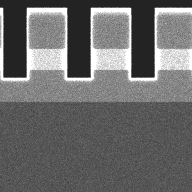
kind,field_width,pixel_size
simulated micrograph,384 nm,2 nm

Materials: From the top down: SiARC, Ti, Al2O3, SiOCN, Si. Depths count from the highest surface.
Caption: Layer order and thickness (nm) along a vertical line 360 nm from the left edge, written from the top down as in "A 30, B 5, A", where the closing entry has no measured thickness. SiARC 14, Ti 68, Al2O3 42, SiOCN 64, Si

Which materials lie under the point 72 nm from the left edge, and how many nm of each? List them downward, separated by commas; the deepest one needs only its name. SiARC 14, Ti 68, Al2O3 42, SiOCN 64, Si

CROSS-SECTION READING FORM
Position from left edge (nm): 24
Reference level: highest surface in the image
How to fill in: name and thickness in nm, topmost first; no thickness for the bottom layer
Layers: empty 140, SiOCN 48, Si